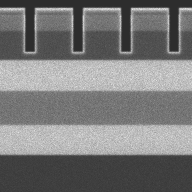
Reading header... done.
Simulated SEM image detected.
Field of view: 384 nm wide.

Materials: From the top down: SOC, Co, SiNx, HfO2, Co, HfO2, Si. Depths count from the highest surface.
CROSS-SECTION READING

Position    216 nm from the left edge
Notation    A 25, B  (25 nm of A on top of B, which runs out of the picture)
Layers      SOC 14, Co 32, SiNx 58, HfO2 62, Co 68, HfO2 60, Si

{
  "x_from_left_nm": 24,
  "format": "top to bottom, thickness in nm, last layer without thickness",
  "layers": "SOC 14, Co 32, SiNx 58, HfO2 62, Co 68, HfO2 60, Si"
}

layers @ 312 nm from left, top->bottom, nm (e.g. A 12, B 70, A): SOC 14, Co 32, SiNx 58, HfO2 62, Co 68, HfO2 60, Si